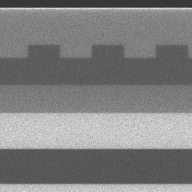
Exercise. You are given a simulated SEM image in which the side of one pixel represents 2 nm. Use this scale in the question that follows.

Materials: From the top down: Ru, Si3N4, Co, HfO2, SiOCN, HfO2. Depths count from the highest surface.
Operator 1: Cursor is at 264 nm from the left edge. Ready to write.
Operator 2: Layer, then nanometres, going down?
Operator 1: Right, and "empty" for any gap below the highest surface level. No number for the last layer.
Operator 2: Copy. Ru 100, Si3N4 54, Co 56, HfO2 72, SiOCN 70, HfO2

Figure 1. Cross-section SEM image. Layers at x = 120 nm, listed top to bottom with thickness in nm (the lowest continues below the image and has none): Ru 100, Si3N4 54, Co 56, HfO2 72, SiOCN 70, HfO2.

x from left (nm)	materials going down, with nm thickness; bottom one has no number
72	Ru 74, Si3N4 80, Co 56, HfO2 72, SiOCN 70, HfO2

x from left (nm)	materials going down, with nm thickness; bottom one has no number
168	Ru 100, Si3N4 54, Co 56, HfO2 72, SiOCN 70, HfO2